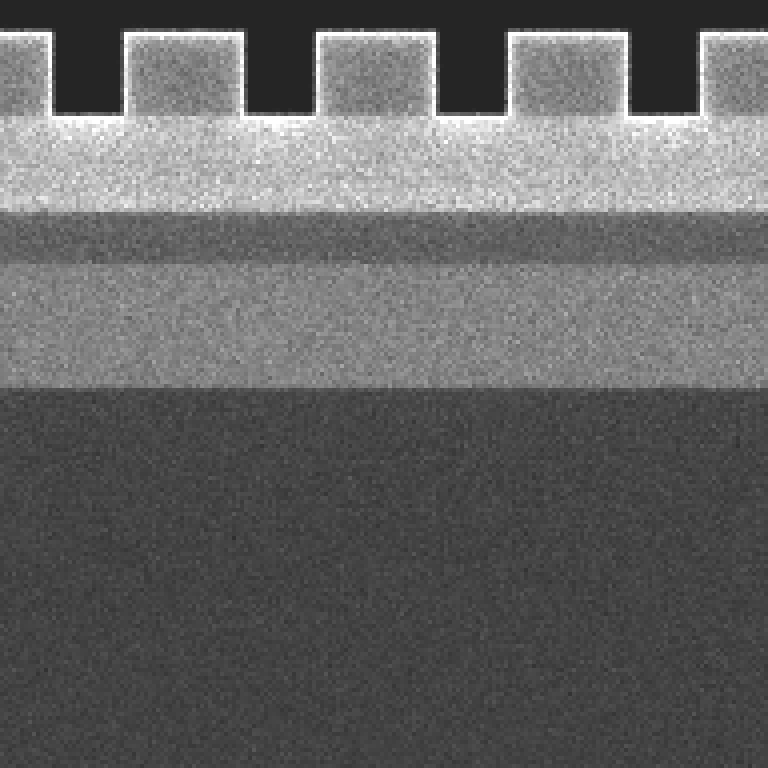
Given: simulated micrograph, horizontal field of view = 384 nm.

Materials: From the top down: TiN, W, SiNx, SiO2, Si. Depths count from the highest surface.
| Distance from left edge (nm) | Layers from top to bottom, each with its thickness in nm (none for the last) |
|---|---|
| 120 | TiN 42, W 48, SiNx 26, SiO2 62, Si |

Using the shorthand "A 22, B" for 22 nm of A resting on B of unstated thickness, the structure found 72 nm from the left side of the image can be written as TiN 42, W 48, SiNx 26, SiO2 62, Si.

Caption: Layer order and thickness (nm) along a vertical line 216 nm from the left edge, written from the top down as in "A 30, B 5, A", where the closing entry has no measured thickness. TiN 42, W 48, SiNx 26, SiO2 62, Si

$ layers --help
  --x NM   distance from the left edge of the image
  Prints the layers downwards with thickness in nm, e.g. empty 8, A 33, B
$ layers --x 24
TiN 42, W 48, SiNx 26, SiO2 62, Si